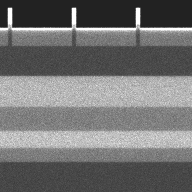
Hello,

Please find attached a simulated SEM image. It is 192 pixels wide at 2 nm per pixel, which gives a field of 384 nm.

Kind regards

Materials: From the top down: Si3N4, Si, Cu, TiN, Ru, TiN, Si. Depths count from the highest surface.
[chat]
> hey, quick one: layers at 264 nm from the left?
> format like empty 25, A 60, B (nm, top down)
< empty 40, Si3N4 36, Si 60, Cu 62, TiN 48, Ru 34, TiN 28, Si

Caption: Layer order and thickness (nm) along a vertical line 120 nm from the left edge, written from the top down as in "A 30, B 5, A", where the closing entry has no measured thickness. empty 40, Si3N4 36, Si 60, Cu 62, TiN 48, Ru 34, TiN 28, Si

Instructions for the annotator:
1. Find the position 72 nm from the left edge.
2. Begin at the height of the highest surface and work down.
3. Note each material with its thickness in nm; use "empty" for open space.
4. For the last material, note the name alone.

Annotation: empty 40, Si3N4 36, Si 60, Cu 62, TiN 48, Ru 34, TiN 28, Si